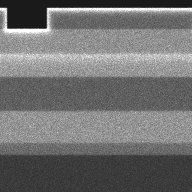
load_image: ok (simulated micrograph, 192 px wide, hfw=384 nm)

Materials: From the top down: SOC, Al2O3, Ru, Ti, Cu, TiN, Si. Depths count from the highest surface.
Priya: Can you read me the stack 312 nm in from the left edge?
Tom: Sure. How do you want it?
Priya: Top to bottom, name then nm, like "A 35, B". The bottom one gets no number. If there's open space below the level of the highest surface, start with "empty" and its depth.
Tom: SOC 42, Al2O3 50, Ru 46, Ti 68, Cu 64, TiN 24, Si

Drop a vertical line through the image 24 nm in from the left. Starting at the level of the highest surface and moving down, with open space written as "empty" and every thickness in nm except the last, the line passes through empty 42, Al2O3 50, Ru 46, Ti 68, Cu 64, TiN 24, Si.